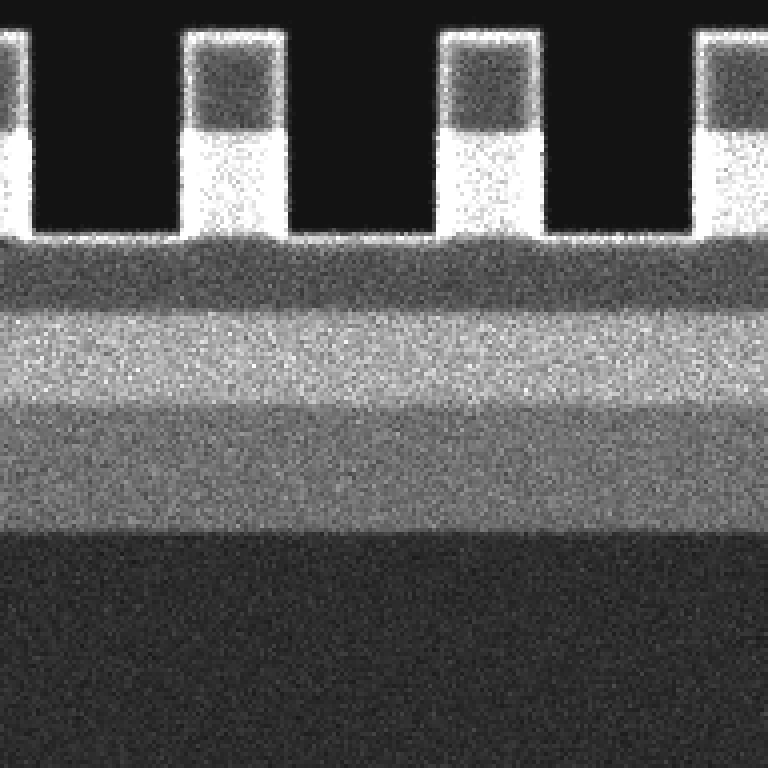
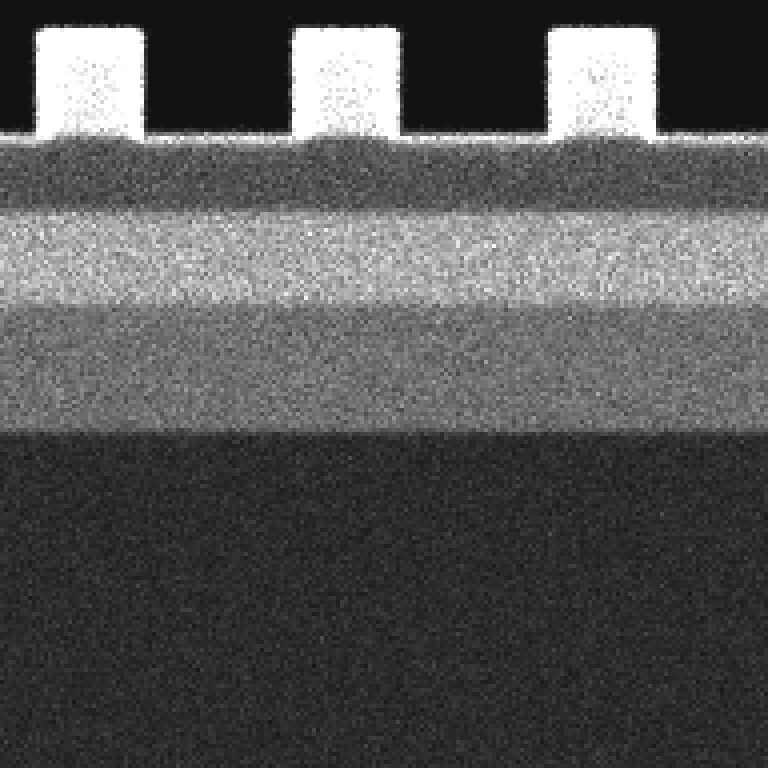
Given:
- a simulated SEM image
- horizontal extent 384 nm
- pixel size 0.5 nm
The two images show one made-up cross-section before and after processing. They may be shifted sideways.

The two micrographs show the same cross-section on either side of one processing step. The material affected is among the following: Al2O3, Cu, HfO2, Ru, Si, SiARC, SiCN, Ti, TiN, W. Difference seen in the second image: SiARC removed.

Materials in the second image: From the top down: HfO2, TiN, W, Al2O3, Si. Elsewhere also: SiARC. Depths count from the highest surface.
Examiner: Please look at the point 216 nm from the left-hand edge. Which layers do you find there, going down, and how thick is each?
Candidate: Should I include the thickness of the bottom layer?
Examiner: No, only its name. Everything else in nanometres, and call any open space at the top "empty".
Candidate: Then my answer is empty 52, TiN 38, W 46, Al2O3 64, Si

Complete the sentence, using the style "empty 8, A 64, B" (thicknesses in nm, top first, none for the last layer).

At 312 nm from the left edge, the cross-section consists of HfO2 52, TiN 38, W 46, Al2O3 64, Si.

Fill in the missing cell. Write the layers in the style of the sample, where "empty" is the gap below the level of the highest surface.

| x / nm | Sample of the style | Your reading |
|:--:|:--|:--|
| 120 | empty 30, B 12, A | empty 52, TiN 38, W 46, Al2O3 64, Si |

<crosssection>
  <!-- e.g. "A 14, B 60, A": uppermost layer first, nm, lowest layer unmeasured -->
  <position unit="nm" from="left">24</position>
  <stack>HfO2 52, TiN 38, W 46, Al2O3 64, Si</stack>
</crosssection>